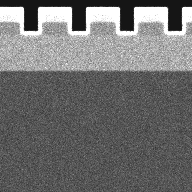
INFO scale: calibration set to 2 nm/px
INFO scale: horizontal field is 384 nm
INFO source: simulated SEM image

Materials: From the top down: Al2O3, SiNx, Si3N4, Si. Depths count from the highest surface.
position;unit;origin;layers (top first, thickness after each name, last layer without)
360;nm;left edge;empty 48, SiNx 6, Si3N4 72, Si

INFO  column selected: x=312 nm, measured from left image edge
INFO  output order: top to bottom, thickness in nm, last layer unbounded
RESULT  Al2O3 28, SiNx 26, Si3N4 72, Si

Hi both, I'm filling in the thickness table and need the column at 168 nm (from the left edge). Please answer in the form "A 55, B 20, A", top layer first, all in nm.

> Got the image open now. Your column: empty 48, SiNx 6, Si3N4 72, Si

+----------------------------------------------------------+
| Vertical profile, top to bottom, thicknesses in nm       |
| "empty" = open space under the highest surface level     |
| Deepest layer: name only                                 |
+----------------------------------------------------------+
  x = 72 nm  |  empty 48, SiNx 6, Si3N4 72, Si